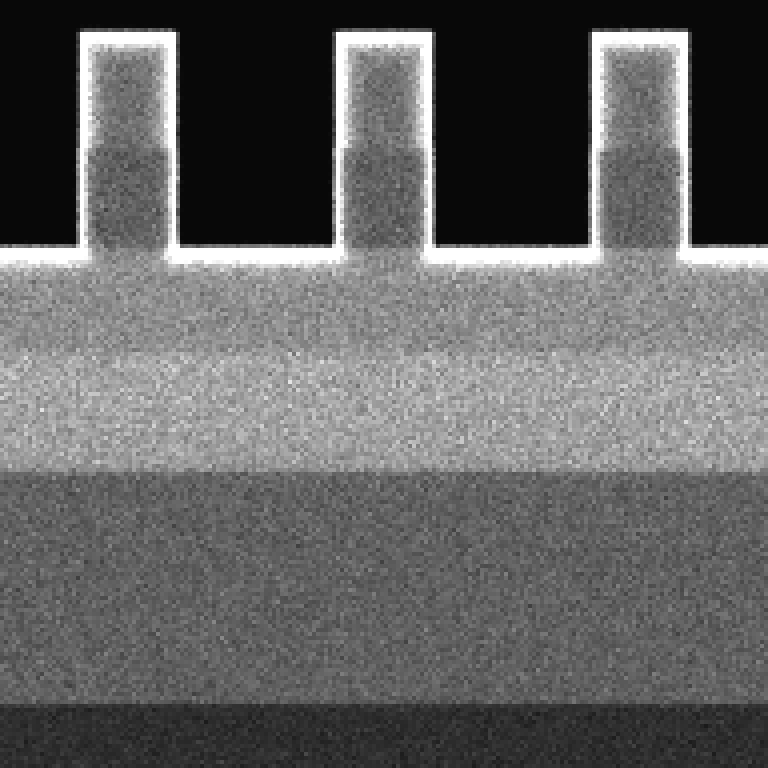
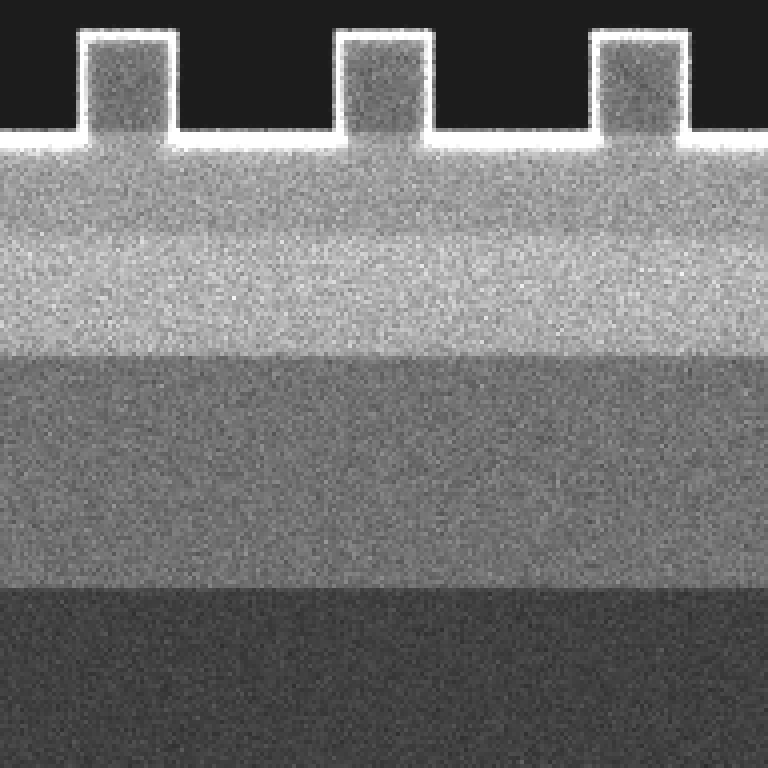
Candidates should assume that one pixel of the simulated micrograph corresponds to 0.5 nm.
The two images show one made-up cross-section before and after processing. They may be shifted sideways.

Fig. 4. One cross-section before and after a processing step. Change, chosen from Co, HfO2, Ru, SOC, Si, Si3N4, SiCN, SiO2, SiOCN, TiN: SOC removed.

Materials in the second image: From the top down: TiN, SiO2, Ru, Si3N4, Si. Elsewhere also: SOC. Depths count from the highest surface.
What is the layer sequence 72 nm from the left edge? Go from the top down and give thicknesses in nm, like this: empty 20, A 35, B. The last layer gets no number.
TiN 50, SiO2 52, Ru 60, Si3N4 116, Si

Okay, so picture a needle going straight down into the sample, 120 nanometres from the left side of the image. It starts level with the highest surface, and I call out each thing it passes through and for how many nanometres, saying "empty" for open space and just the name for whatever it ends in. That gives empty 50, SiO2 52, Ru 60, Si3N4 116, Si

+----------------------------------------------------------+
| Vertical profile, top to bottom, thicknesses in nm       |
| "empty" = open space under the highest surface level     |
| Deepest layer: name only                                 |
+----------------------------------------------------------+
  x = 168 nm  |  TiN 50, SiO2 52, Ru 60, Si3N4 116, Si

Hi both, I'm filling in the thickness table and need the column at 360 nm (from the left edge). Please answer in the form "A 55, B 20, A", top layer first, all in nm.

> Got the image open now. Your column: empty 50, SiO2 52, Ru 60, Si3N4 116, Si